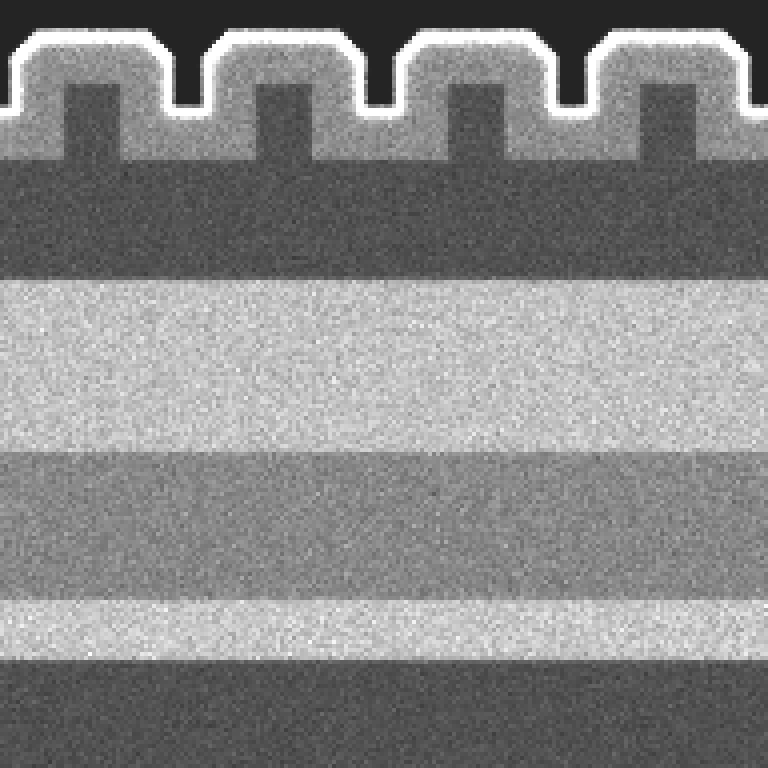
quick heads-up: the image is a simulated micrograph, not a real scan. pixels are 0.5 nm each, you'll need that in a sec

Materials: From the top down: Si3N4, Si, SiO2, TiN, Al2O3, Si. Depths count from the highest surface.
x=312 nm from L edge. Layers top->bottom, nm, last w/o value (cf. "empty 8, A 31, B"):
Si3N4 64, Si 60, SiO2 86, TiN 74, Al2O3 30, Si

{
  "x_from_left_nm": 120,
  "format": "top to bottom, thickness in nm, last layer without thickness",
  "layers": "Si3N4 64, Si 60, SiO2 86, TiN 74, Al2O3 30, Si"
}